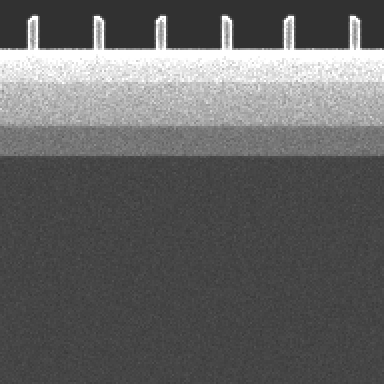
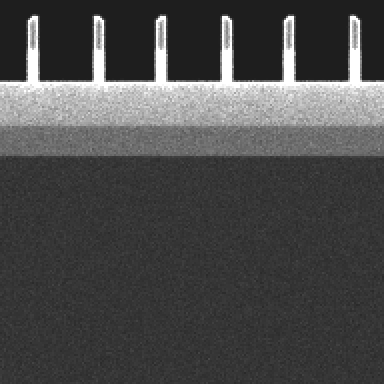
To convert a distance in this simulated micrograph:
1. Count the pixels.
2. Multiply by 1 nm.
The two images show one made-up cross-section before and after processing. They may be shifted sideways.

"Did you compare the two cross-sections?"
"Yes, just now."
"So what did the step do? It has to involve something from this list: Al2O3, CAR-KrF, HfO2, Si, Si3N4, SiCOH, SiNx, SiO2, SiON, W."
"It removed HfO2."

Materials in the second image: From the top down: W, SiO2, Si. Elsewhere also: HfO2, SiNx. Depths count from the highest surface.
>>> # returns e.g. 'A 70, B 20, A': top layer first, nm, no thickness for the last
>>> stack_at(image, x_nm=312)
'empty 66, W 44, SiO2 30, Si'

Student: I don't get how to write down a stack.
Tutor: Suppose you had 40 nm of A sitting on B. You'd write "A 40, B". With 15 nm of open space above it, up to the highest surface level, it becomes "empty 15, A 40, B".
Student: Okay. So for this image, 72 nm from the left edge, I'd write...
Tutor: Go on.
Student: empty 66, W 44, SiO2 30, Si